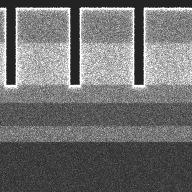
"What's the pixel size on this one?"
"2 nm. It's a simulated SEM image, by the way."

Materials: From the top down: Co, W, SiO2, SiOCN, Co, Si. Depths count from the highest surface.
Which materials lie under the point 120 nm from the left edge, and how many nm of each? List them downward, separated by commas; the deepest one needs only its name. Co 70, W 84, SiO2 36, SiOCN 46, Co 32, Si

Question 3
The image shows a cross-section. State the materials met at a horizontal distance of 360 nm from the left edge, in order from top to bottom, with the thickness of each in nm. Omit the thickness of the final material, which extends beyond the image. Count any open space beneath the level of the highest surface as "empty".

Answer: Co 70, W 84, SiO2 36, SiOCN 46, Co 32, Si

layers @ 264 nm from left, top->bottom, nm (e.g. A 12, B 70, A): Co 70, W 84, SiO2 36, SiOCN 46, Co 32, Si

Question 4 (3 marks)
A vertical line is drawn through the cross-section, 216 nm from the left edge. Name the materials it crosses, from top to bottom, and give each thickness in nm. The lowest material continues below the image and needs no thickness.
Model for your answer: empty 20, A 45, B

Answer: Co 70, W 84, SiO2 36, SiOCN 46, Co 32, Si